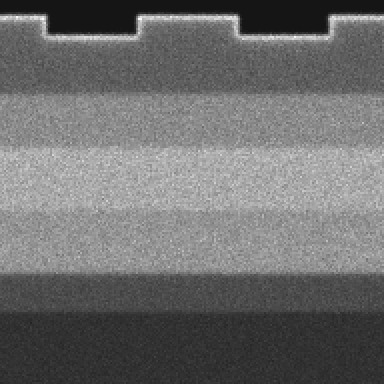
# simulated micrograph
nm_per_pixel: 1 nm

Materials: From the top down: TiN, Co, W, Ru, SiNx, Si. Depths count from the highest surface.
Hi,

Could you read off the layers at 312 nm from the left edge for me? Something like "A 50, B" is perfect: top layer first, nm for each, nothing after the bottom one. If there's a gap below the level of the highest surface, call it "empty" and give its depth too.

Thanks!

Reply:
empty 20, TiN 58, Co 54, W 62, Ru 64, SiNx 38, Si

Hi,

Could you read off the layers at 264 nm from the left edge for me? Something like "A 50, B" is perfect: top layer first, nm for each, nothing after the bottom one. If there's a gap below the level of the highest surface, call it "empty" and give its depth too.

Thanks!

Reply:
empty 20, TiN 58, Co 54, W 62, Ru 64, SiNx 38, Si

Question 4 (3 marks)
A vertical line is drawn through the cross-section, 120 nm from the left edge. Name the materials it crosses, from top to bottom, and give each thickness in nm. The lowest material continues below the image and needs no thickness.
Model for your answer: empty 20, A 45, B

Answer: empty 20, TiN 58, Co 54, W 62, Ru 64, SiNx 38, Si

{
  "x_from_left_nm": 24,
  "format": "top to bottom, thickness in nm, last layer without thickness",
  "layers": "TiN 78, Co 54, W 62, Ru 64, SiNx 38, Si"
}